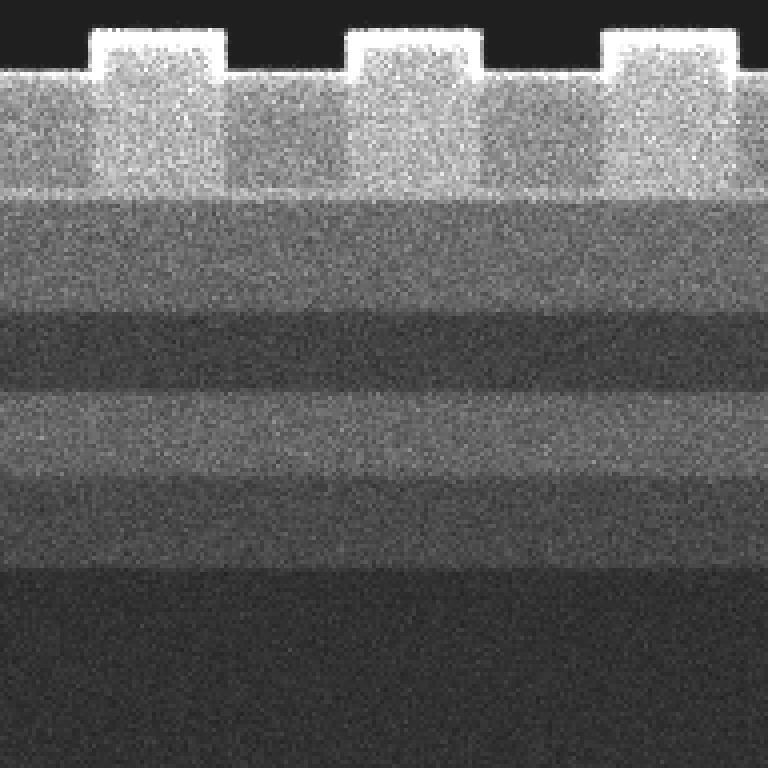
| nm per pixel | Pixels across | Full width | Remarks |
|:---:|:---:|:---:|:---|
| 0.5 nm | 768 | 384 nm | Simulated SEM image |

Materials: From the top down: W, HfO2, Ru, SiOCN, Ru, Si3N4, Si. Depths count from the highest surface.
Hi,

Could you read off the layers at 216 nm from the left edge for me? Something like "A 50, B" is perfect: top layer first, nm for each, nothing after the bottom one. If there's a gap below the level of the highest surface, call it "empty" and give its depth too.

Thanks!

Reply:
HfO2 84, Ru 56, SiOCN 40, Ru 42, Si3N4 46, Si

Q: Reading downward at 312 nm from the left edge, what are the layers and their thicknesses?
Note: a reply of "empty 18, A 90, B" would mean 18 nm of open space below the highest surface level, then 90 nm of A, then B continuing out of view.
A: HfO2 84, Ru 56, SiOCN 40, Ru 42, Si3N4 46, Si